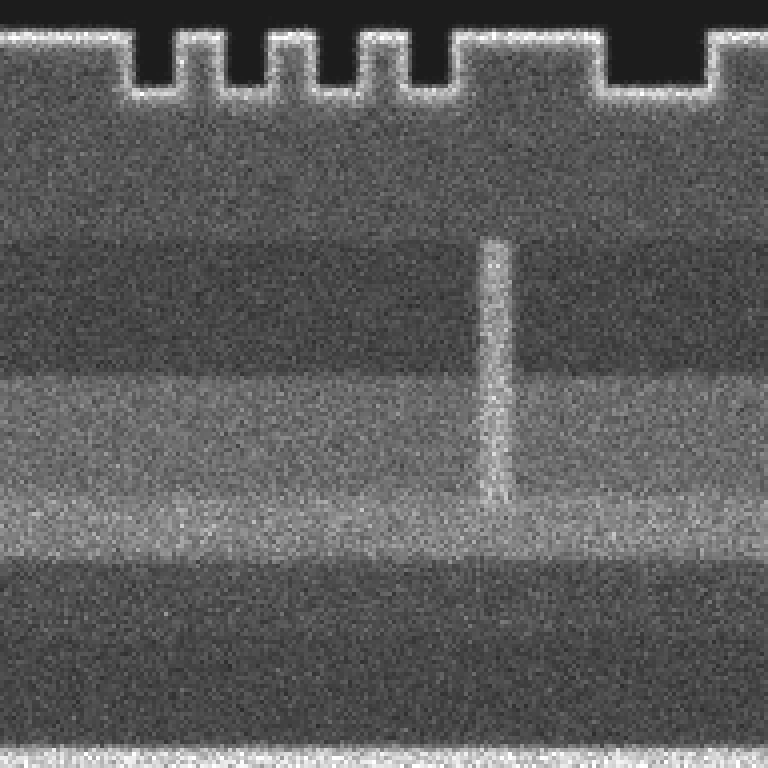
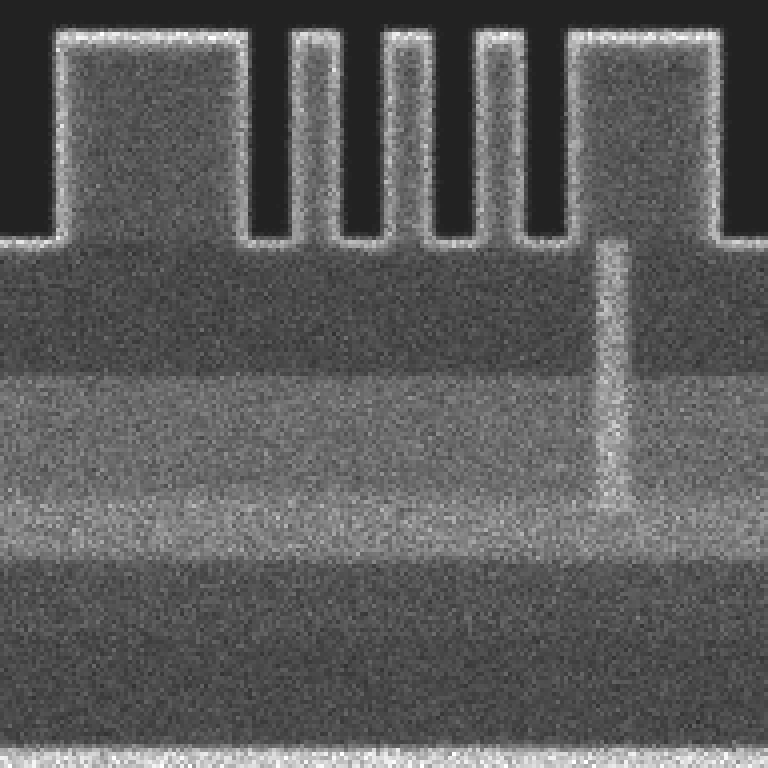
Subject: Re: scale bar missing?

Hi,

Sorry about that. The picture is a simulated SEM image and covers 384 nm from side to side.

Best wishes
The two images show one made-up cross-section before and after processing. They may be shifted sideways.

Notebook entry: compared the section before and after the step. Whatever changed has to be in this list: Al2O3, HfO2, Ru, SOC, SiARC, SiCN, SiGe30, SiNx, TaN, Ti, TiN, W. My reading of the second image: SOC removed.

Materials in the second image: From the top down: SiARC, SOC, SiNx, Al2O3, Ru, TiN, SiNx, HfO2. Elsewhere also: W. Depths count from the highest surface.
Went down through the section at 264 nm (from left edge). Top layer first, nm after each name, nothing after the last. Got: empty 104, SiNx 68, Al2O3 60, Ru 32, TiN 38, SiNx 56, HfO2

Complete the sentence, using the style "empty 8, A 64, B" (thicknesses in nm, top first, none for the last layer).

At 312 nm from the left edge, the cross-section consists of SiARC 28, SOC 76, W 136, Ru 24, TiN 38, SiNx 56, HfO2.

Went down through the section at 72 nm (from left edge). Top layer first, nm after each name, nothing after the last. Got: SiARC 28, SOC 76, SiNx 68, Al2O3 60, Ru 32, TiN 38, SiNx 56, HfO2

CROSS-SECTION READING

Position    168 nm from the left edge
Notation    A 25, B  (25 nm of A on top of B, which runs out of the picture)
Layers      SiARC 28, SOC 76, SiNx 68, Al2O3 60, Ru 32, TiN 38, SiNx 56, HfO2